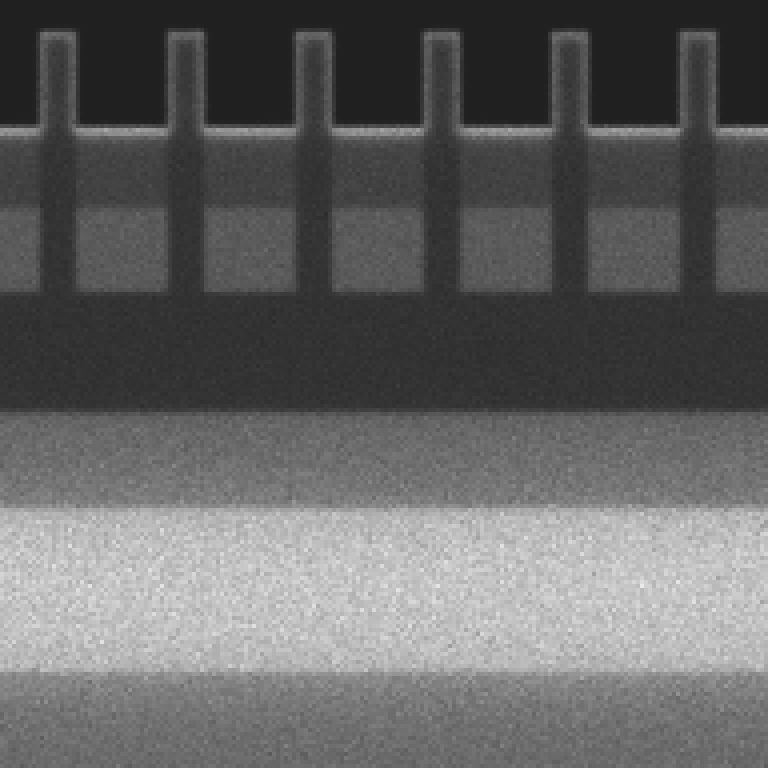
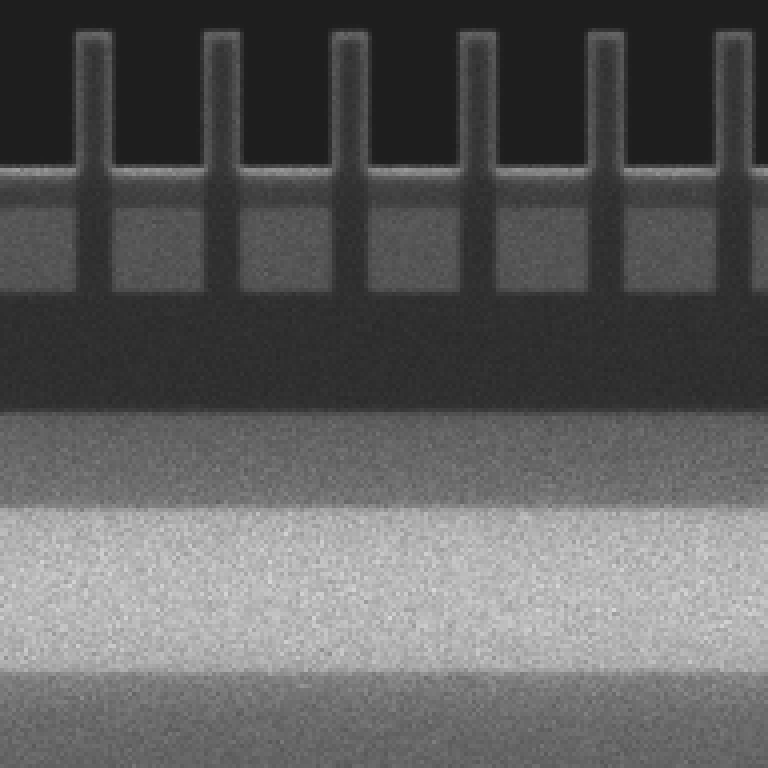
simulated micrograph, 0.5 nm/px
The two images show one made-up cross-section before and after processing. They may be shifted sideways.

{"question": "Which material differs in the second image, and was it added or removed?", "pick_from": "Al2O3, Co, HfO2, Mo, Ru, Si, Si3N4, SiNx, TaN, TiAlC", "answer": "SiNx, removed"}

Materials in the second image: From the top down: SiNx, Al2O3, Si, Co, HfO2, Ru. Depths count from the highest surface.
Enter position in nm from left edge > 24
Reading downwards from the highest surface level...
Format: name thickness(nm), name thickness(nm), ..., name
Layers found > empty 68, SiNx 20, Al2O3 42, Si 60, Co 48, HfO2 82, Ru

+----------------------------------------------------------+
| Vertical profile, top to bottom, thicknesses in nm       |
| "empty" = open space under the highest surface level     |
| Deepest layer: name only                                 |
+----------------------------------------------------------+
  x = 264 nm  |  empty 68, SiNx 20, Al2O3 42, Si 60, Co 48, HfO2 82, Ru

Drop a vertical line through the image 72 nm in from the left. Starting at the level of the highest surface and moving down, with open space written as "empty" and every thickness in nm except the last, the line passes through empty 68, SiNx 20, Al2O3 42, Si 60, Co 48, HfO2 82, Ru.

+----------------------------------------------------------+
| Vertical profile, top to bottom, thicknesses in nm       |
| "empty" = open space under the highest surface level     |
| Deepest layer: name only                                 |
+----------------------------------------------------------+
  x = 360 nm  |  Si 190, Co 48, HfO2 82, Ru